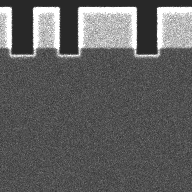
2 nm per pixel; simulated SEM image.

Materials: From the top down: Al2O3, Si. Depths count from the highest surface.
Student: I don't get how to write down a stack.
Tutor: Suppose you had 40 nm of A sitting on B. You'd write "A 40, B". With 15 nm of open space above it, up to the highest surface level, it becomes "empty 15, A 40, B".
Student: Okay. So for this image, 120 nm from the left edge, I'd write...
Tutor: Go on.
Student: empty 94, Si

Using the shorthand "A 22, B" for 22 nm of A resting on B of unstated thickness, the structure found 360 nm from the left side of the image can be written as Al2O3 80, Si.